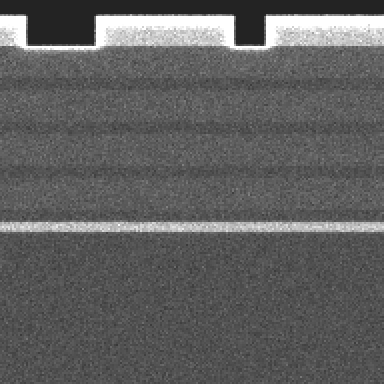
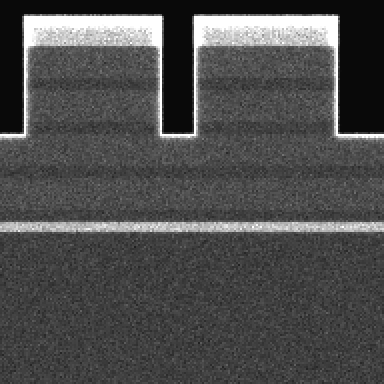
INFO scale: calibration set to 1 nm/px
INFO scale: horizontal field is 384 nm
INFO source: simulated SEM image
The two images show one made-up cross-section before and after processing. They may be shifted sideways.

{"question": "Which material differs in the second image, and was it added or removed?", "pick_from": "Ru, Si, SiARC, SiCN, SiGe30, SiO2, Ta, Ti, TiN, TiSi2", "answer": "Si and SiGe30, removed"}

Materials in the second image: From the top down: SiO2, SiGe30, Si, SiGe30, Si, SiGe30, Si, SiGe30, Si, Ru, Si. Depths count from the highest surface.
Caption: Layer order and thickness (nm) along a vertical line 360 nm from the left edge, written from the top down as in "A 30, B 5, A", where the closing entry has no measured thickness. empty 118, SiGe30 32, Si 12, SiGe30 32, Si 12, Ru 10, Si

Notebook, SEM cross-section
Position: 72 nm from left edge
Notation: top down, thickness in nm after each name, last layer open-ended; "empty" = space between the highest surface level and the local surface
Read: SiO2 30, SiGe30 32, Si 12, SiGe30 32, Si 12, SiGe30 32, Si 12, SiGe30 32, Si 12, Ru 10, Si